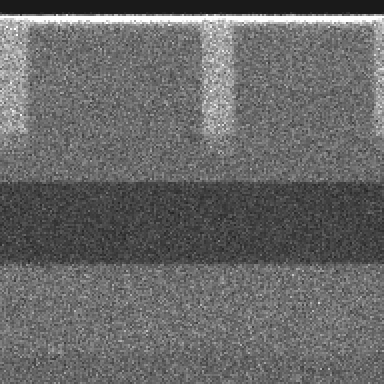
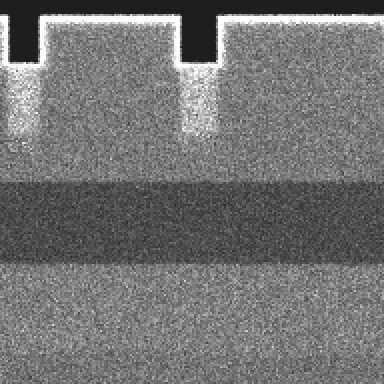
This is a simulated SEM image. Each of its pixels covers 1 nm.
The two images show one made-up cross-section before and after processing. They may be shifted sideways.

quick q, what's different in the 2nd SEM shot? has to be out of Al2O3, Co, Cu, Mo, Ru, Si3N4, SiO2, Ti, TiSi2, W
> W removed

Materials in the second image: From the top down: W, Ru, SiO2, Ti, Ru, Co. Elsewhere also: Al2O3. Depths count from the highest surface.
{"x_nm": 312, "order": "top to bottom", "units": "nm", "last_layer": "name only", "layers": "Al2O3 88, SiO2 78, Ti 82, Ru 90, Co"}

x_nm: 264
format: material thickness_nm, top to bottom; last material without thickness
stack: Al2O3 88, SiO2 78, Ti 82, Ru 90, Co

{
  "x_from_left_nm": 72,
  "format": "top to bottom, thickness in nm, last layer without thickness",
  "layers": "Al2O3 88, SiO2 78, Ti 82, Ru 90, Co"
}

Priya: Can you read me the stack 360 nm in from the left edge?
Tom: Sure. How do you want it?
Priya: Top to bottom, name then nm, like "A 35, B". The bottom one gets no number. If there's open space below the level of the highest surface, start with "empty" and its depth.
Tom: Al2O3 88, SiO2 78, Ti 82, Ru 90, Co